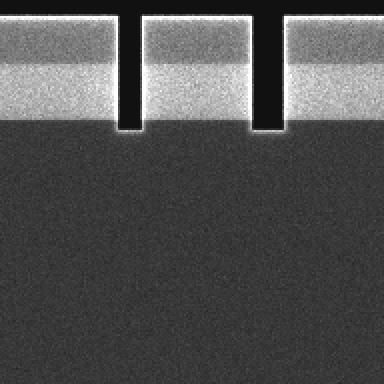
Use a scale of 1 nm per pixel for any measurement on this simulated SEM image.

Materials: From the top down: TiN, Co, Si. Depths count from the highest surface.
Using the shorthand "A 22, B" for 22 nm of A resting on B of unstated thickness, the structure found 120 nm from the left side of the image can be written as empty 114, Si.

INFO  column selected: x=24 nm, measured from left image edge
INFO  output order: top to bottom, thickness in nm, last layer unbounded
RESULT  TiN 48, Co 56, Si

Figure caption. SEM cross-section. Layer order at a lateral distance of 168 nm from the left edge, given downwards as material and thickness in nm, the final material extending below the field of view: TiN 48, Co 56, Si